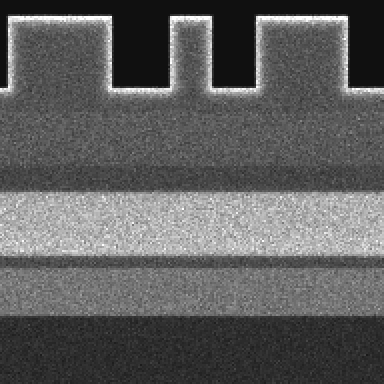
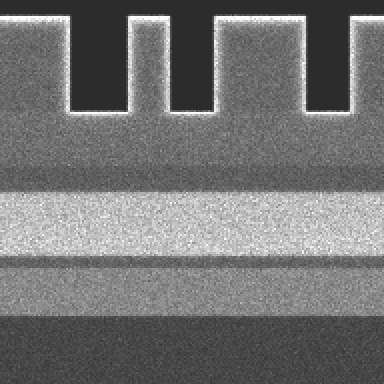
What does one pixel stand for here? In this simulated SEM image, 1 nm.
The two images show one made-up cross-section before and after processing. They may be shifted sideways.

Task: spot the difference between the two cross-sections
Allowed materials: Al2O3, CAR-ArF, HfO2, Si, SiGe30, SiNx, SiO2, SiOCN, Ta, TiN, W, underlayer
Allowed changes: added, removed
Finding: removed underlayer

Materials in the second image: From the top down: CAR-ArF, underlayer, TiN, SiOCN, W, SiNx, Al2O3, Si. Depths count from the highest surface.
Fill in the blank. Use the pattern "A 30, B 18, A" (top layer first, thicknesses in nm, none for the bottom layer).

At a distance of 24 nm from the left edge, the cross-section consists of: CAR-ArF 72, underlayer 24, TiN 54, SiOCN 26, W 64, SiNx 12, Al2O3 48, Si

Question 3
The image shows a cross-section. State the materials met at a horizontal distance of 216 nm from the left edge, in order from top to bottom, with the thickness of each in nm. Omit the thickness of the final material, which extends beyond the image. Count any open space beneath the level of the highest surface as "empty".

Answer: CAR-ArF 72, underlayer 24, TiN 54, SiOCN 26, W 64, SiNx 12, Al2O3 48, Si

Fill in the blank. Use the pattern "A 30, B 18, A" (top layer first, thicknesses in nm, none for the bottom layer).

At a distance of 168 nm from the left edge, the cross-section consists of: CAR-ArF 72, underlayer 24, TiN 54, SiOCN 26, W 64, SiNx 12, Al2O3 48, Si